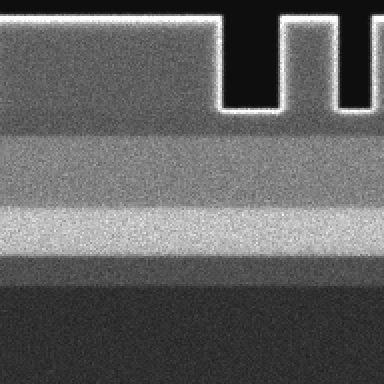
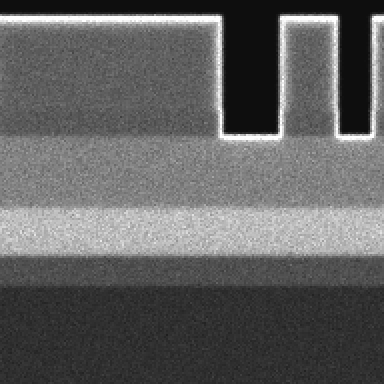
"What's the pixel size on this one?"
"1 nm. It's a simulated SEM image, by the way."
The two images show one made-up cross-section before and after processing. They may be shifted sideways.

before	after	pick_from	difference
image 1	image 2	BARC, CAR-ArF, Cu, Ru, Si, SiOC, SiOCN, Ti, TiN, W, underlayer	TiN removed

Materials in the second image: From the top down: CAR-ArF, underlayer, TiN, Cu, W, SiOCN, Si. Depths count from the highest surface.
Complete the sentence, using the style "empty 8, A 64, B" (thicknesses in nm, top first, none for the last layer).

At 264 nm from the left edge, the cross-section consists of empty 120, Cu 72, W 48, SiOCN 30, Si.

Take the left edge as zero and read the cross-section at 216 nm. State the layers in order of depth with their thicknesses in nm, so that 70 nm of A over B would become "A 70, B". CAR-ArF 44, underlayer 50, TiN 26, Cu 72, W 48, SiOCN 30, Si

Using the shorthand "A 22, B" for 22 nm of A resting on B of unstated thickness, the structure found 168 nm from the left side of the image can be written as CAR-ArF 44, underlayer 50, TiN 26, Cu 72, W 48, SiOCN 30, Si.